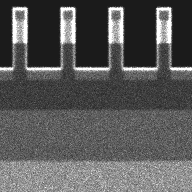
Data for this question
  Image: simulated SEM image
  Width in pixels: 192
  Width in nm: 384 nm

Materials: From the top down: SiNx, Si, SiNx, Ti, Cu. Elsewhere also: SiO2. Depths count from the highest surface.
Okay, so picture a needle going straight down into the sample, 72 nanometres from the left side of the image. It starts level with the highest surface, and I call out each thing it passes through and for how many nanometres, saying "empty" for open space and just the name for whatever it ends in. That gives empty 120, SiNx 24, Si 60, SiNx 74, Ti 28, Cu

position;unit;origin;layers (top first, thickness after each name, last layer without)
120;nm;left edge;empty 120, SiNx 24, Si 60, SiNx 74, Ti 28, Cu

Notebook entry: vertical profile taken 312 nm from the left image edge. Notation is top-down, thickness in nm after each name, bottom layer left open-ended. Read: empty 120, SiNx 24, Si 60, SiNx 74, Ti 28, Cu